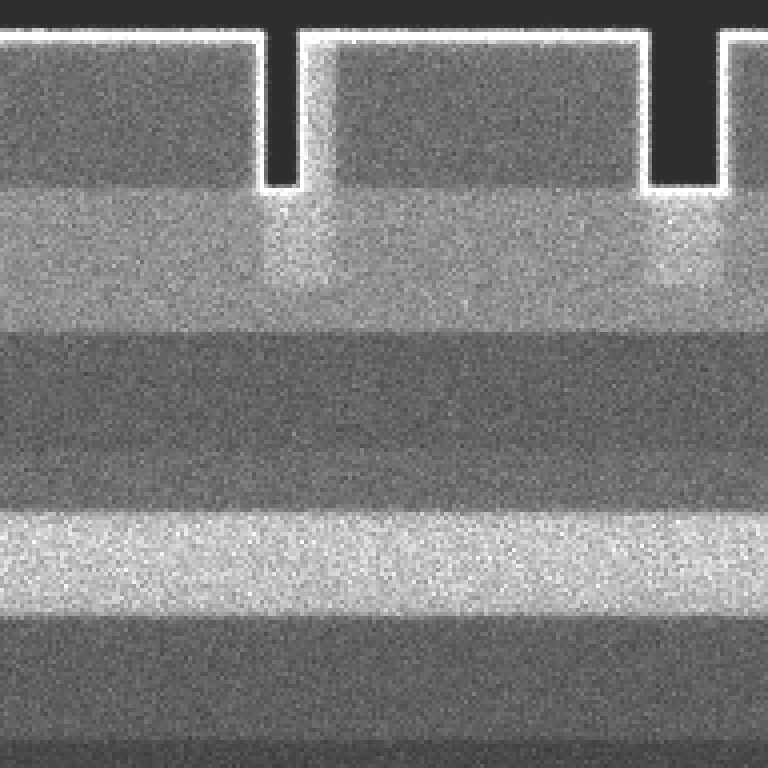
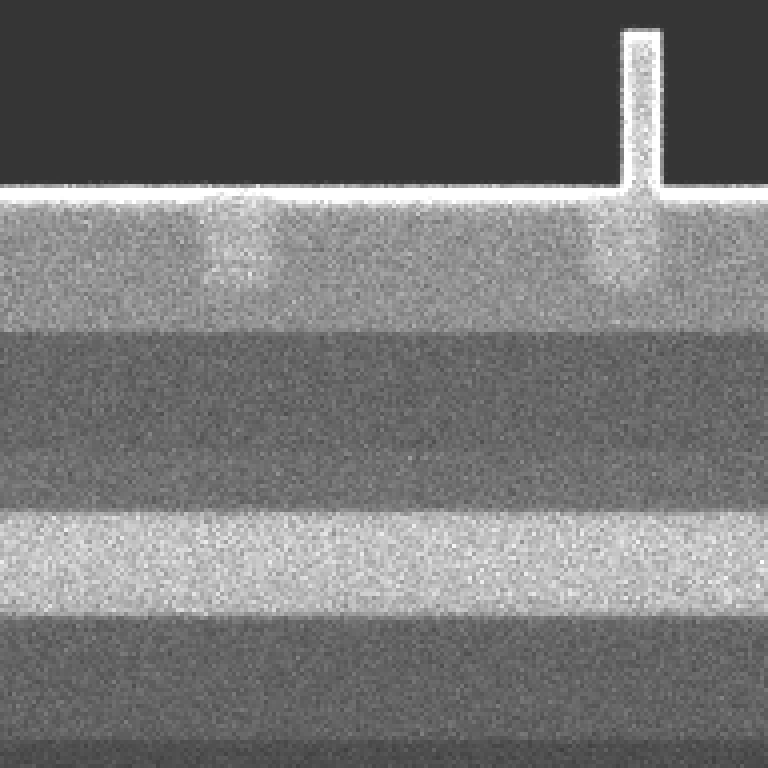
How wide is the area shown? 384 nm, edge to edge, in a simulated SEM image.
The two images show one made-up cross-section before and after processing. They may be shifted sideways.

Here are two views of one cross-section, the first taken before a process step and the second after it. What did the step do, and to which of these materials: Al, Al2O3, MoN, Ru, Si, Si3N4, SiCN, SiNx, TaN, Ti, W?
It removed Si3N4.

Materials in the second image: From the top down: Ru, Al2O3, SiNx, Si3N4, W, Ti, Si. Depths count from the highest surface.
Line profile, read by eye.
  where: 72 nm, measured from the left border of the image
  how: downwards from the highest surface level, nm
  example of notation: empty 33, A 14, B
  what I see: empty 78, Al2O3 72, SiNx 60, Si3N4 30, W 52, Ti 62, Si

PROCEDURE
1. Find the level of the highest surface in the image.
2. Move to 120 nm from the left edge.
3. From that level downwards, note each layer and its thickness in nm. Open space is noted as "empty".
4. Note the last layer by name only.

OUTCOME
empty 78, Ru 50, Al2O3 22, SiNx 60, Si3N4 30, W 52, Ti 62, Si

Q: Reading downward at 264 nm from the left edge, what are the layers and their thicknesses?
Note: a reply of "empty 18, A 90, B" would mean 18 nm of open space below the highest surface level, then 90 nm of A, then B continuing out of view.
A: empty 78, Al2O3 72, SiNx 60, Si3N4 30, W 52, Ti 62, Si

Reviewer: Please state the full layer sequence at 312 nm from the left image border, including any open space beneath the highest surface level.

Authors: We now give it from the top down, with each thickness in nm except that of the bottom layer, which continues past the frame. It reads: Ru 128, Al2O3 22, SiNx 60, Si3N4 30, W 52, Ti 62, Si